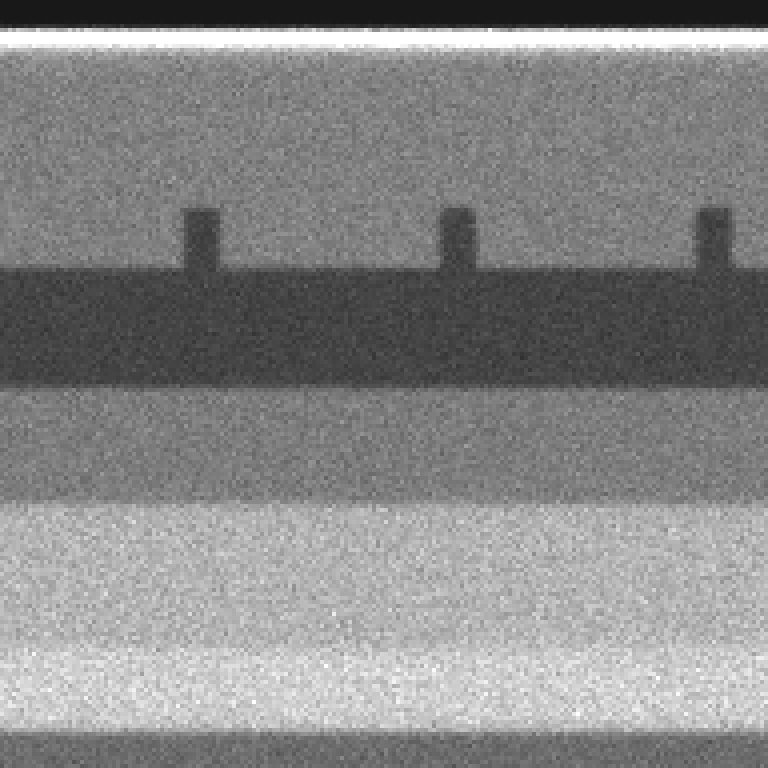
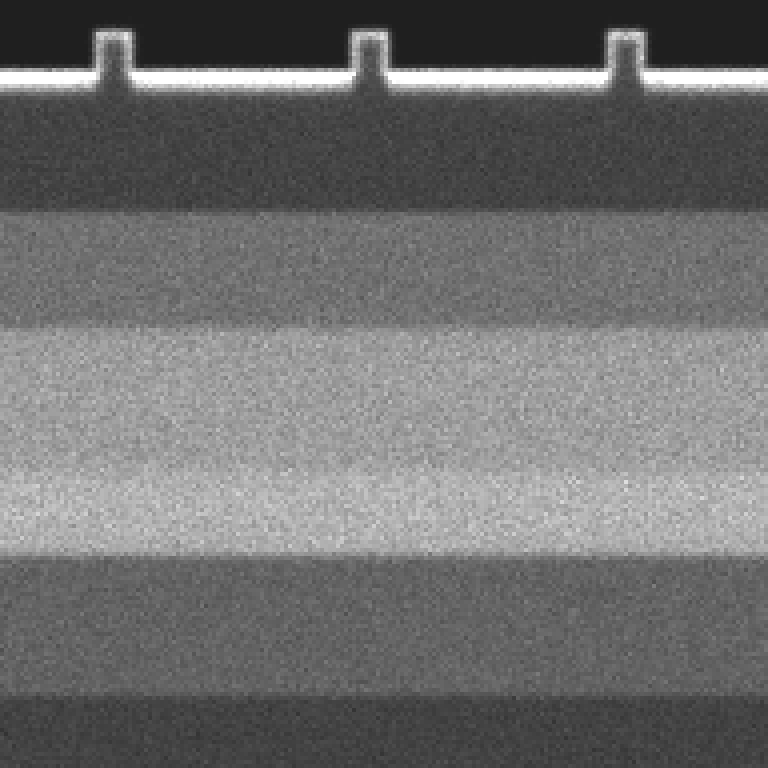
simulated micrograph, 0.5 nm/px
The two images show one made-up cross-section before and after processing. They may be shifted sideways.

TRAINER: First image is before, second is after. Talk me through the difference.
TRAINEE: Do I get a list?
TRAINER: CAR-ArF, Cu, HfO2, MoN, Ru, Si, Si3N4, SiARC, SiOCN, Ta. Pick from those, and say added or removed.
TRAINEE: removed: SiARC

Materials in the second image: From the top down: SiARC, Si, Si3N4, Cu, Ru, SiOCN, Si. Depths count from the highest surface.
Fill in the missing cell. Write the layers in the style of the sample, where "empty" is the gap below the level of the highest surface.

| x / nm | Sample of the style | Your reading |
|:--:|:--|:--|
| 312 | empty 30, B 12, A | Si 90, Si3N4 58, Cu 72, Ru 42, SiOCN 70, Si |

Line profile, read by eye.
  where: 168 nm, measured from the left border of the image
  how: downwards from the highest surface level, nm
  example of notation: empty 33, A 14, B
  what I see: empty 20, SiARC 10, Si 60, Si3N4 58, Cu 72, Ru 42, SiOCN 70, Si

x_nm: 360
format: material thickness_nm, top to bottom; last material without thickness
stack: empty 20, SiARC 10, Si 60, Si3N4 58, Cu 72, Ru 42, SiOCN 70, Si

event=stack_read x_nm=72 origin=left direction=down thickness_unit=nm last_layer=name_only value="empty 20, SiARC 10, Si 60, Si3N4 58, Cu 72, Ru 42, SiOCN 70, Si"